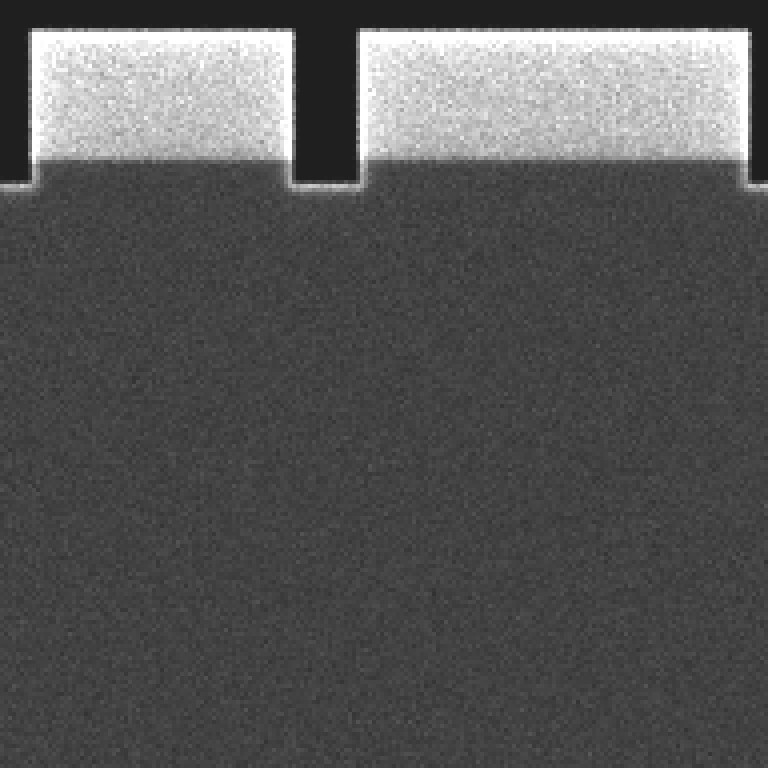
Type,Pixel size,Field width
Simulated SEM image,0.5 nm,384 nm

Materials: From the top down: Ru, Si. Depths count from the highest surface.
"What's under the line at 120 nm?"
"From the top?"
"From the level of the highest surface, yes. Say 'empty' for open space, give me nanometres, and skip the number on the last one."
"Ru 64, Si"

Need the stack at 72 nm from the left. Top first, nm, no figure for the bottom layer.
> Ru 64, Si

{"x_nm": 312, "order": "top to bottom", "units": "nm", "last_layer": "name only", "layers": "Ru 64, Si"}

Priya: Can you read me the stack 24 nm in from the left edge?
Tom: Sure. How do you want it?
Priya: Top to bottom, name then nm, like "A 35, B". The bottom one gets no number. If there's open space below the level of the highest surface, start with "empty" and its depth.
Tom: Ru 64, Si